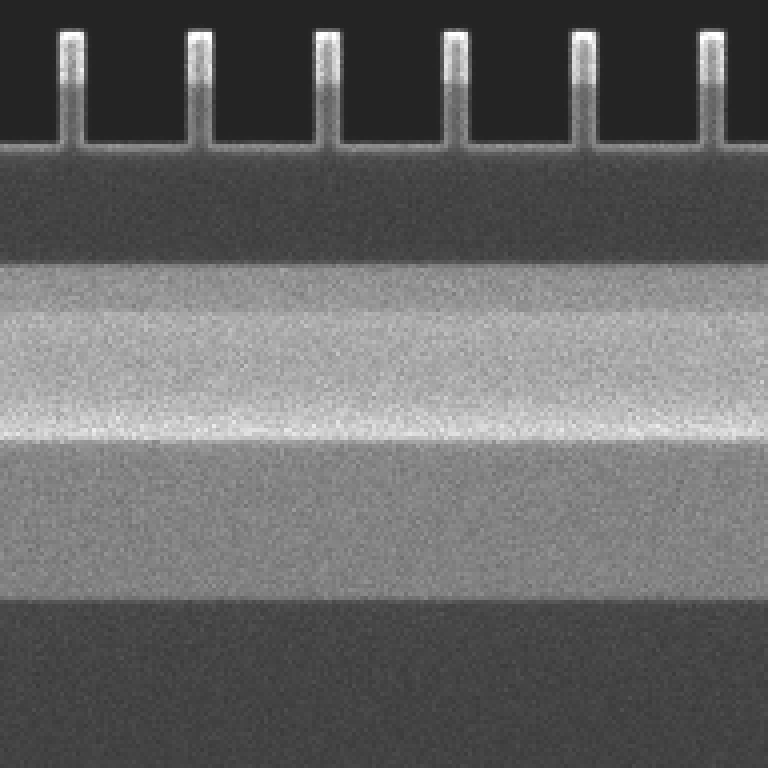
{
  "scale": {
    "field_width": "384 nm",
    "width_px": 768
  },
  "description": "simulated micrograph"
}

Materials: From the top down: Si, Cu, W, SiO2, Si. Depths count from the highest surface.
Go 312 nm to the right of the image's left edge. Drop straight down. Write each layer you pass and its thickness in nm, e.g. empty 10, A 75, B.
empty 56, Si 60, Cu 24, W 64, SiO2 80, Si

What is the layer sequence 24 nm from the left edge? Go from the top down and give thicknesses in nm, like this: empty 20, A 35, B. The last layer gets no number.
empty 56, Si 60, Cu 24, W 64, SiO2 80, Si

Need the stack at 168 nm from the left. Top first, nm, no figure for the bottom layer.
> Si 116, Cu 24, W 64, SiO2 80, Si